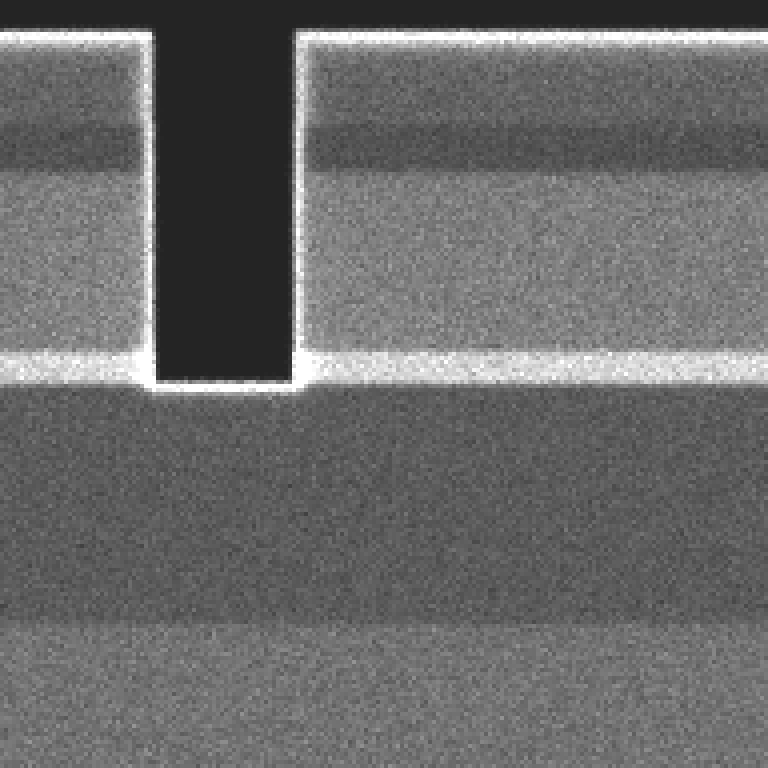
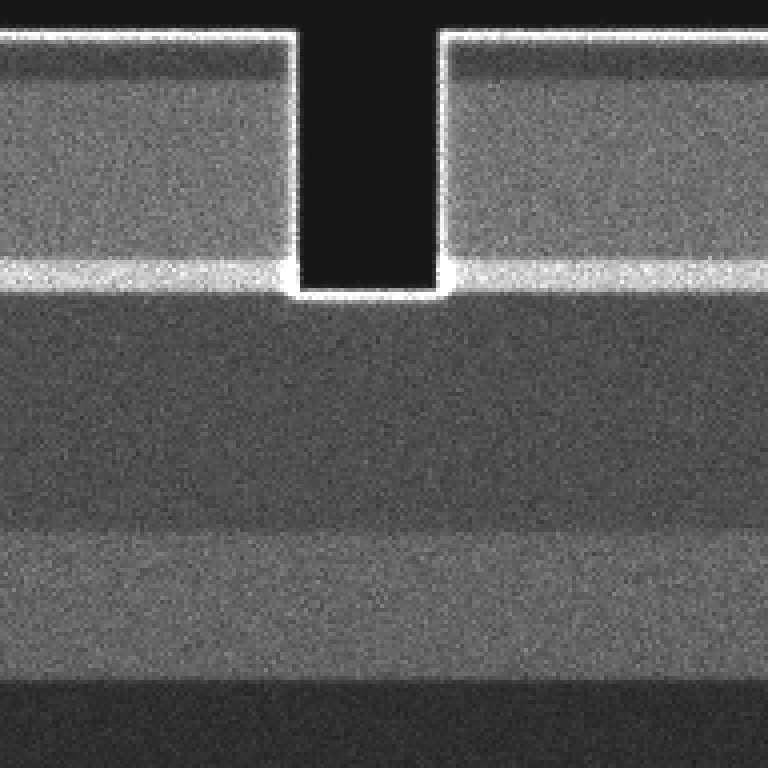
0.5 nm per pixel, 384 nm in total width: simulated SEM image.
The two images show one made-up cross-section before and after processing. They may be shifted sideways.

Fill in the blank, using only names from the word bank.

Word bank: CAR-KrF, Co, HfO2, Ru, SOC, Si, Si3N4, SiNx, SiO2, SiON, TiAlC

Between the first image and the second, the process removed SOC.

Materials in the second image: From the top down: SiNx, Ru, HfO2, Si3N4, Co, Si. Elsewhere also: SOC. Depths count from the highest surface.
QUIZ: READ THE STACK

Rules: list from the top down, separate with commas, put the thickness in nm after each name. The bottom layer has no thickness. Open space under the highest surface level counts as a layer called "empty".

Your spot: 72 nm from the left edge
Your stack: SiNx 24, Ru 90, HfO2 16, Si3N4 120, Co 74, Si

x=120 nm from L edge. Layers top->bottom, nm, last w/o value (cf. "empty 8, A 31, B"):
SiNx 24, Ru 90, HfO2 16, Si3N4 120, Co 74, Si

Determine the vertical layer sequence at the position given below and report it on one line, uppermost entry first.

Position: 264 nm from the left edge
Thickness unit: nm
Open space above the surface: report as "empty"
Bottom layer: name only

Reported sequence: SiNx 24, Ru 90, HfO2 16, Si3N4 120, Co 74, Si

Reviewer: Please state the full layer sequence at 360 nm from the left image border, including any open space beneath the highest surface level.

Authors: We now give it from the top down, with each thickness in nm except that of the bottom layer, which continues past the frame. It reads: SiNx 24, Ru 90, HfO2 16, Si3N4 120, Co 74, Si